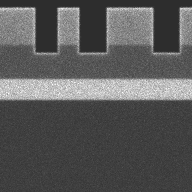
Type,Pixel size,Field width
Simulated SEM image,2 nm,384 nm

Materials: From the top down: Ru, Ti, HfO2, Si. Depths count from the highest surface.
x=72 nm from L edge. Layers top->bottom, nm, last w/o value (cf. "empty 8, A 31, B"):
empty 90, Ti 52, HfO2 42, Si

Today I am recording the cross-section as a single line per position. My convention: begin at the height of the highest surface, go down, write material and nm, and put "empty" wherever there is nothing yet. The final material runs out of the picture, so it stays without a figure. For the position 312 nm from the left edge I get empty 90, Ti 52, HfO2 42, Si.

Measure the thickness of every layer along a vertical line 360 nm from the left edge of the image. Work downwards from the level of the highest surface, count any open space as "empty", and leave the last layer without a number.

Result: Ru 74, Ti 68, HfO2 42, Si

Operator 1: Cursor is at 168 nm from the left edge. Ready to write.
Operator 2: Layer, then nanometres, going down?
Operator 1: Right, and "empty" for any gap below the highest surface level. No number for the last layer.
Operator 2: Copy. empty 90, Ti 52, HfO2 42, Si